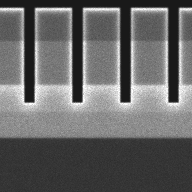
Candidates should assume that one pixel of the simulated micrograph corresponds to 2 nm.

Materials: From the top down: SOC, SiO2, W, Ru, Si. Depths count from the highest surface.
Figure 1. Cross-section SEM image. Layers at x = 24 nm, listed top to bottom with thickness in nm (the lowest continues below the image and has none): SOC 66, SiO2 88, W 54, Ru 52, Si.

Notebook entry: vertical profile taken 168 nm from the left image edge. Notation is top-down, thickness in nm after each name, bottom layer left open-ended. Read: SOC 66, SiO2 88, W 54, Ru 52, Si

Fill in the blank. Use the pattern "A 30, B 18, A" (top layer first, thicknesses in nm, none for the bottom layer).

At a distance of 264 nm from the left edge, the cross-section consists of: SOC 66, SiO2 88, W 54, Ru 52, Si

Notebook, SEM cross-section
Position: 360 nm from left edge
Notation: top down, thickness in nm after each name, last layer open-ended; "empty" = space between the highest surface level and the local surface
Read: SOC 66, SiO2 88, W 54, Ru 52, Si